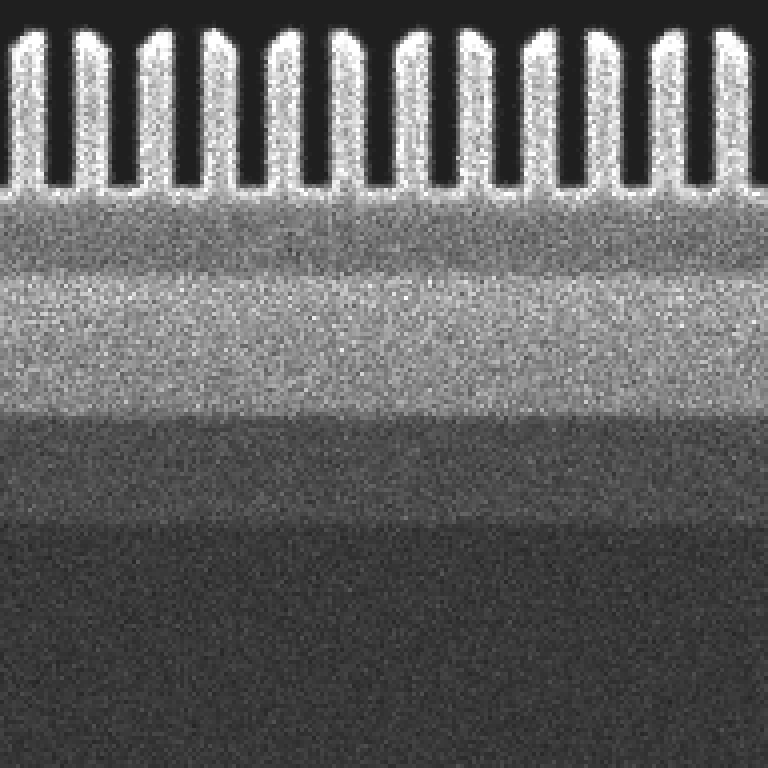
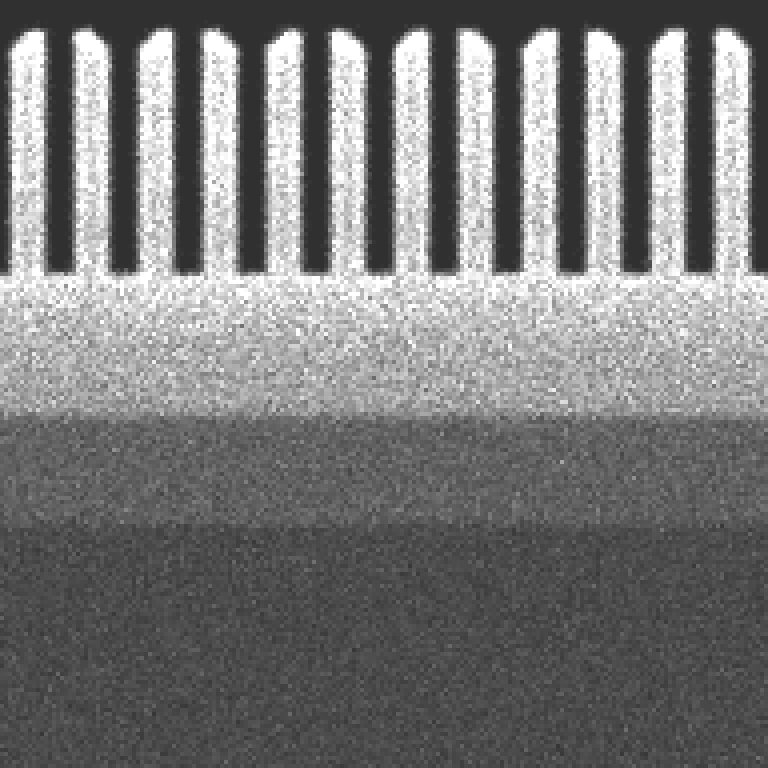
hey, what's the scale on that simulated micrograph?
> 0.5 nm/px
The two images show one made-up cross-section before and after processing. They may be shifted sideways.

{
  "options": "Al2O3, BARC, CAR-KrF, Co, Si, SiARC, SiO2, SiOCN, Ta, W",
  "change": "removed",
  "material": "SiO2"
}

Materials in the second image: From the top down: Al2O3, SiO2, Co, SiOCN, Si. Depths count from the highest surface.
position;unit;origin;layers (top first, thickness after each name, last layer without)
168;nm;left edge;Al2O3 78, SiO2 44, Co 70, SiOCN 54, Si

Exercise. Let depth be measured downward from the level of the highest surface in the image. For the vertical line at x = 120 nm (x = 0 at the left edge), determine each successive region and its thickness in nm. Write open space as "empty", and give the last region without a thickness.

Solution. empty 122, Co 70, SiOCN 54, Si